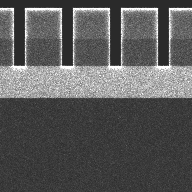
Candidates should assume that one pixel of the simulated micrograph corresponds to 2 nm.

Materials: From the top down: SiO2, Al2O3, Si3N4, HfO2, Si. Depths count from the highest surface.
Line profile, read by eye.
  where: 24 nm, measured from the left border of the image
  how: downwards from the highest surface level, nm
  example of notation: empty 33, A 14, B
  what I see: SiO2 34, Al2O3 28, Si3N4 54, HfO2 64, Si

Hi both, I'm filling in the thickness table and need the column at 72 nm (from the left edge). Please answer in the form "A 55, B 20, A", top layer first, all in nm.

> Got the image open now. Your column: SiO2 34, Al2O3 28, Si3N4 54, HfO2 64, Si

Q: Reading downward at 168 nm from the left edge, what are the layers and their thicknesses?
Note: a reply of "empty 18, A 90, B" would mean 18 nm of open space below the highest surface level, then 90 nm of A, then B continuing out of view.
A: SiO2 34, Al2O3 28, Si3N4 54, HfO2 64, Si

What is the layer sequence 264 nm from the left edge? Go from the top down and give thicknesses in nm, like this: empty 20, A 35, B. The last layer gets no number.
SiO2 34, Al2O3 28, Si3N4 54, HfO2 64, Si